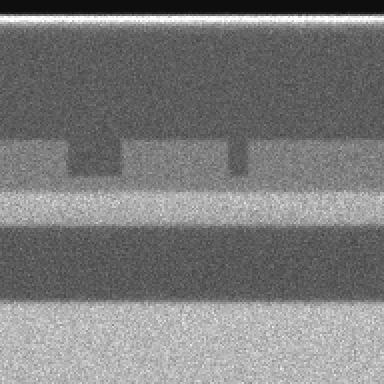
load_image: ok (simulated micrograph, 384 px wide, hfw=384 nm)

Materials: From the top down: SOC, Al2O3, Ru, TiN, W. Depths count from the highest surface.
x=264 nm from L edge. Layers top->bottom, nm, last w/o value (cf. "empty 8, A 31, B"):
SOC 124, Al2O3 52, Ru 34, TiN 76, W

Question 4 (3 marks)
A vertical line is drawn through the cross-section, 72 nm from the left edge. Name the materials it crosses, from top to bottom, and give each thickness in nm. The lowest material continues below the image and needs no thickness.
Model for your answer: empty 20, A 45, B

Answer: SOC 160, Al2O3 16, Ru 34, TiN 76, W